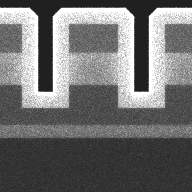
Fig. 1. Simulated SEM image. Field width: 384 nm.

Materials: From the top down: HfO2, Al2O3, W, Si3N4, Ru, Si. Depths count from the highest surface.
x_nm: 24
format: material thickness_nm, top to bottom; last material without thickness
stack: HfO2 32, Al2O3 58, W 64, Si3N4 80, Ru 26, Si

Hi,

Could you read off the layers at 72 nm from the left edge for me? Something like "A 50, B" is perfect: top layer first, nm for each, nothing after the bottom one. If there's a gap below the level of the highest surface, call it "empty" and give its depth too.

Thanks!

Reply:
empty 14, HfO2 186, Si3N4 34, Ru 26, Si